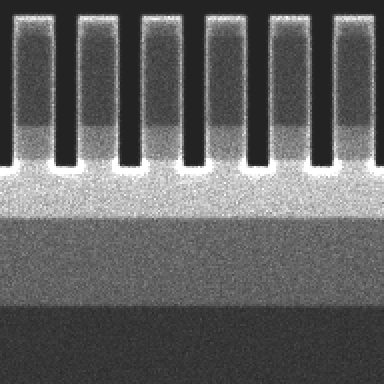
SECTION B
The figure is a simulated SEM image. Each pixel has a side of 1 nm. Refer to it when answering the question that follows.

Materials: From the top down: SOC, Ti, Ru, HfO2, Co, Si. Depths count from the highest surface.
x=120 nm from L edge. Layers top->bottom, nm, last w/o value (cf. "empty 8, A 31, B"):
empty 152, HfO2 50, Co 88, Si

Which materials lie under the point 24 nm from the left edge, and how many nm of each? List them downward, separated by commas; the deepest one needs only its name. SOC 20, Ti 90, Ru 34, HfO2 58, Co 88, Si